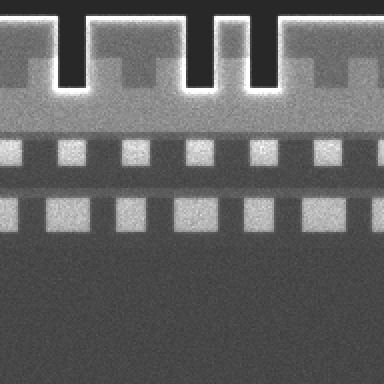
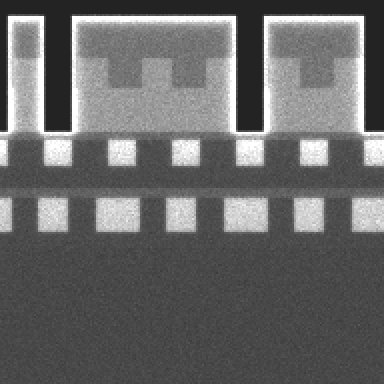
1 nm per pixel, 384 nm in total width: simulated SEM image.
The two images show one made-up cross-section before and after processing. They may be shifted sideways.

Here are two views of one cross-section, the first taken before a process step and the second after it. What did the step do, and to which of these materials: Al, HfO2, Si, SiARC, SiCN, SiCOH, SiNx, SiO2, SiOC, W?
It removed SiO2.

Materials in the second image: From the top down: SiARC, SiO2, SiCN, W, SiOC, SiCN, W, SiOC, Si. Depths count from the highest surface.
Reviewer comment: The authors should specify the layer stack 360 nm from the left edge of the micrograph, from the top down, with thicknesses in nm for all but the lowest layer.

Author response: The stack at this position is SiARC 42, SiO2 74, SiCN 8, SiOC 48, SiCN 10, W 34, SiOC 16, Si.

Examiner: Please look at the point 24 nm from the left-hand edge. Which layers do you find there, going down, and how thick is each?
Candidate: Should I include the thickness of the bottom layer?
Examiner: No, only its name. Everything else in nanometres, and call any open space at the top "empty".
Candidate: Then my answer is SiARC 42, SiO2 74, SiCN 8, SiOC 48, SiCN 10, SiOC 50, Si